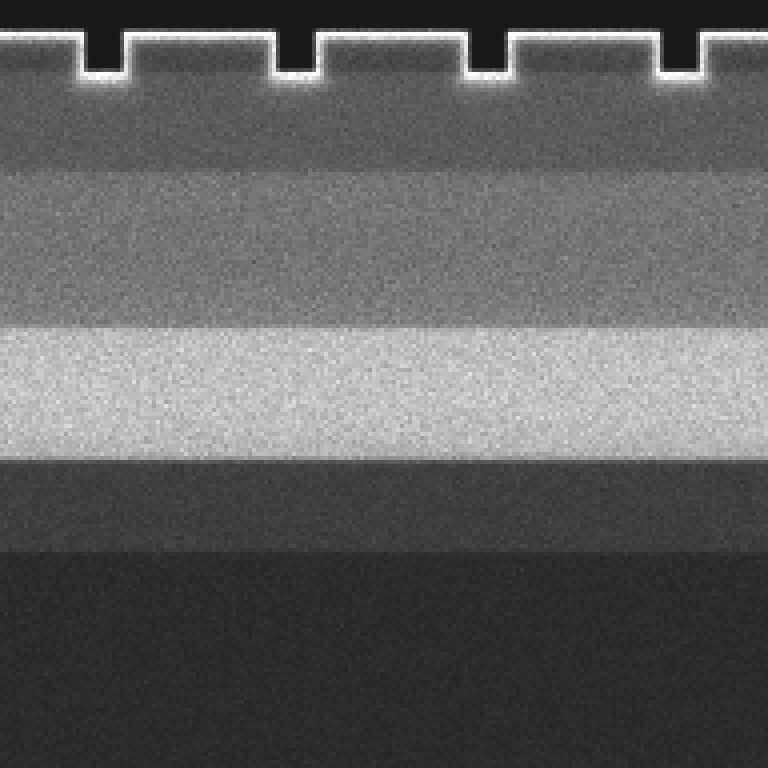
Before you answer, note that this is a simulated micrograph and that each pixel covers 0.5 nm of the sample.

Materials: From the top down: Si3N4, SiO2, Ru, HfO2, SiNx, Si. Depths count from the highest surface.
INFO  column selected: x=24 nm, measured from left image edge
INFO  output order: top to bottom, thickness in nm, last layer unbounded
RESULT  Si3N4 20, SiO2 50, Ru 78, HfO2 66, SiNx 46, Si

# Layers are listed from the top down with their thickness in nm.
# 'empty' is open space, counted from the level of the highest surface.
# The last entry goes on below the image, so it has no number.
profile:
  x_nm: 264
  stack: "Si3N4 20, SiO2 50, Ru 78, HfO2 66, SiNx 46, Si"